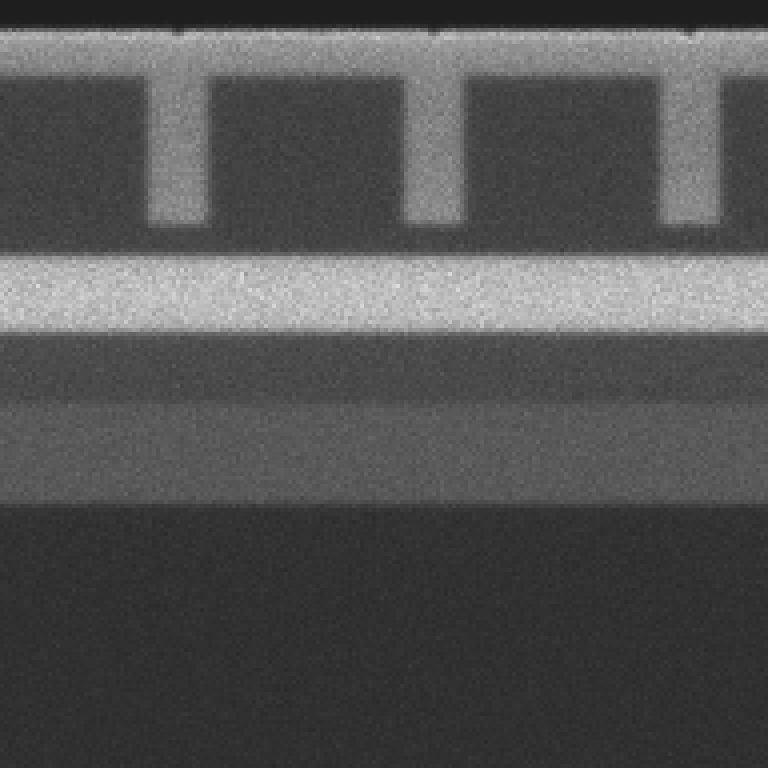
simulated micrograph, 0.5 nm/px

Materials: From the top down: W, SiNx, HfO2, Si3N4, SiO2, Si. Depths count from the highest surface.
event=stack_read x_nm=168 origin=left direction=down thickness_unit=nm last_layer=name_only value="W 22, SiNx 90, HfO2 38, Si3N4 36, SiO2 50, Si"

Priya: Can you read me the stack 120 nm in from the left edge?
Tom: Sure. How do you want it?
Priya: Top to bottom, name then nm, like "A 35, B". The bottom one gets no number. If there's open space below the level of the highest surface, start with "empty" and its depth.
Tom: W 22, SiNx 90, HfO2 38, Si3N4 36, SiO2 50, Si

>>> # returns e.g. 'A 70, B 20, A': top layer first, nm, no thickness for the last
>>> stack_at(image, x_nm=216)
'empty 2, W 94, SiNx 16, HfO2 38, Si3N4 36, SiO2 50, Si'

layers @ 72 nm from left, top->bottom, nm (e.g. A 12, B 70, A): W 22, SiNx 90, HfO2 38, Si3N4 36, SiO2 50, Si